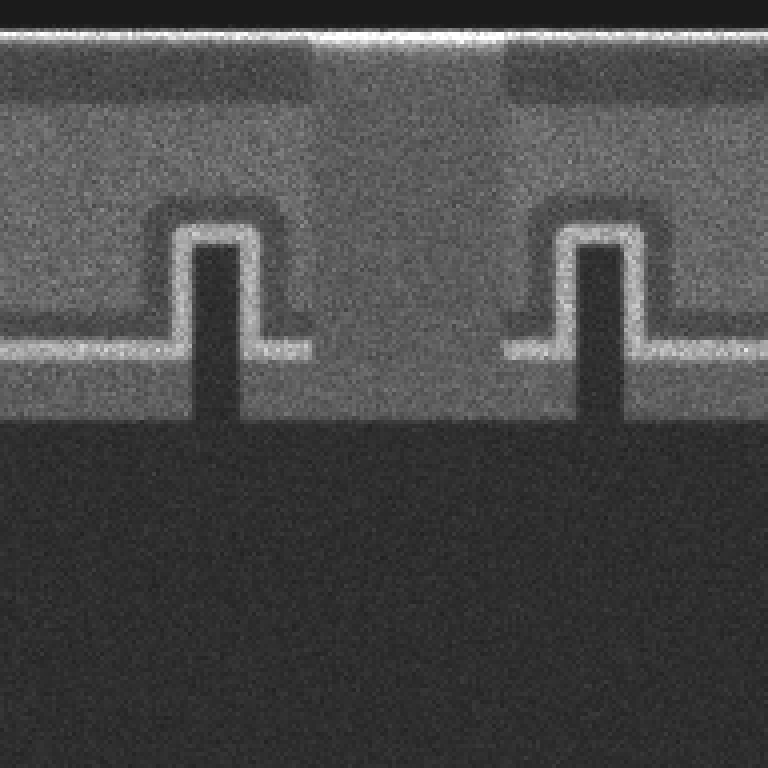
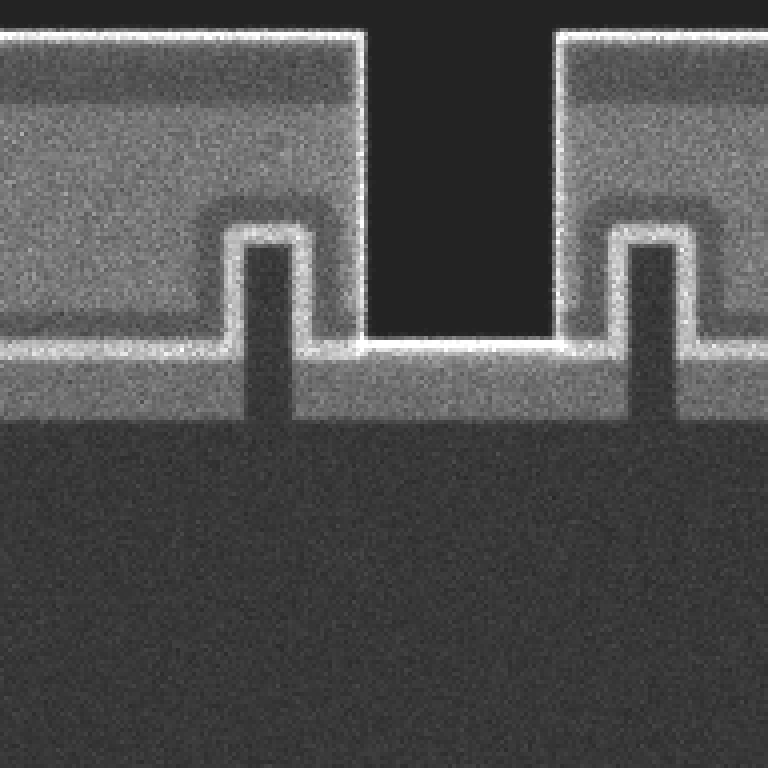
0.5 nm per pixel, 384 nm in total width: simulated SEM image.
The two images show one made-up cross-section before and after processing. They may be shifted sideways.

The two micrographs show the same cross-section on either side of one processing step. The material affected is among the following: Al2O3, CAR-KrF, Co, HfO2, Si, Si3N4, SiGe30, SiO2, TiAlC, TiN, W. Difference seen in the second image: SiO2 removed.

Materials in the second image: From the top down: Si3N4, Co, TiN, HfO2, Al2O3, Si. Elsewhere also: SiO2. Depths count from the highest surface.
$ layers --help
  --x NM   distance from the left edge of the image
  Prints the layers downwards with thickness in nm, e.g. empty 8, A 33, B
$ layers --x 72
Si3N4 36, Co 104, TiN 14, HfO2 10, Al2O3 30, Si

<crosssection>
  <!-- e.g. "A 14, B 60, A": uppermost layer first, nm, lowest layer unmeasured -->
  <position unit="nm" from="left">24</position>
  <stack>Si3N4 36, Co 104, TiN 14, HfO2 10, Al2O3 30, Si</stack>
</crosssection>